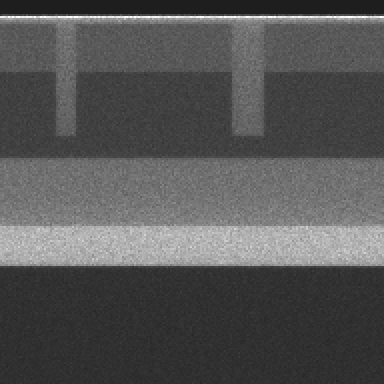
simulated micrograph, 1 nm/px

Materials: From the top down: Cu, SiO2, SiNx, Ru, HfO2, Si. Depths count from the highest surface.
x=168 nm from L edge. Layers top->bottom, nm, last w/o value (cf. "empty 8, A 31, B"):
Cu 8, SiO2 48, SiNx 86, Ru 68, HfO2 40, Si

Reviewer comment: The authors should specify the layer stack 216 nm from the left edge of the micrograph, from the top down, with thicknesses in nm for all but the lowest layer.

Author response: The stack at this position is Cu 8, SiO2 48, SiNx 86, Ru 68, HfO2 40, Si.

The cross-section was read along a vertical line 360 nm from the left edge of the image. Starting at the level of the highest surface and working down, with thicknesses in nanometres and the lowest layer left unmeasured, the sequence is Cu 8, SiO2 48, SiNx 86, Ru 68, HfO2 40, Si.